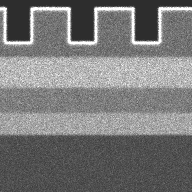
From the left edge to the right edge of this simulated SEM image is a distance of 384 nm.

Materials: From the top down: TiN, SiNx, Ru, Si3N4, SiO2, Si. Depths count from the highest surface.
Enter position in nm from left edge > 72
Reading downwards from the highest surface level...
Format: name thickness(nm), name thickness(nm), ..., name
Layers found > TiN 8, SiNx 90, Ru 62, Si3N4 50, SiO2 44, Si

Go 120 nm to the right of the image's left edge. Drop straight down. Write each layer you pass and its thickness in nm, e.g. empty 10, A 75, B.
TiN 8, SiNx 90, Ru 62, Si3N4 50, SiO2 44, Si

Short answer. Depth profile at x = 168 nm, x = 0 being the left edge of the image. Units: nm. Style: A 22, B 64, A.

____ empty 68, SiNx 30, Ru 62, Si3N4 50, SiO2 44, Si